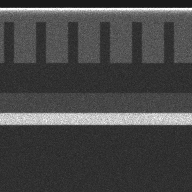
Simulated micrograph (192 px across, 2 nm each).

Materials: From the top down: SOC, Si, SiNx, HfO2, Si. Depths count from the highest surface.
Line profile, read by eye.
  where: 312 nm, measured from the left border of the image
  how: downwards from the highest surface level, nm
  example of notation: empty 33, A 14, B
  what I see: SOC 110, Si 60, SiNx 40, HfO2 24, Si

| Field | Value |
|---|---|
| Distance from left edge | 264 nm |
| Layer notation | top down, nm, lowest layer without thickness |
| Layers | SOC 28, Si 142, SiNx 40, HfO2 24, Si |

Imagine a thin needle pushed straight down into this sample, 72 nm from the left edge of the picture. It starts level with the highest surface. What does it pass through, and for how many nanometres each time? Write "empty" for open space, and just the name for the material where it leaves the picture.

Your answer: SOC 28, Si 142, SiNx 40, HfO2 24, Si